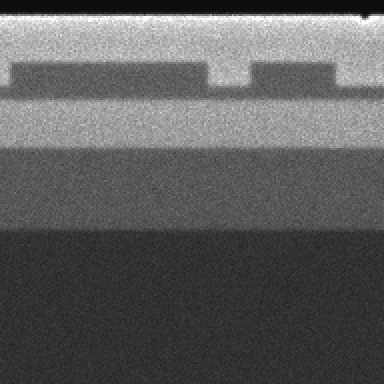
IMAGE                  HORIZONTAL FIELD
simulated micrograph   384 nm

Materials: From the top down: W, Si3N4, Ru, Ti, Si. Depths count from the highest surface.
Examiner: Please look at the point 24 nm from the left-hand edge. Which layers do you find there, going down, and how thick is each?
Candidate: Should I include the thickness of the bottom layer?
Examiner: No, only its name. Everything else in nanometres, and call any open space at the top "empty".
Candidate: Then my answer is W 46, Si3N4 38, Ru 48, Ti 82, Si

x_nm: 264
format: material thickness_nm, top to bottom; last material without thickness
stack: W 46, Si3N4 38, Ru 48, Ti 82, Si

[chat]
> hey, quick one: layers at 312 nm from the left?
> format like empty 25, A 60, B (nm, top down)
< W 46, Si3N4 38, Ru 48, Ti 82, Si